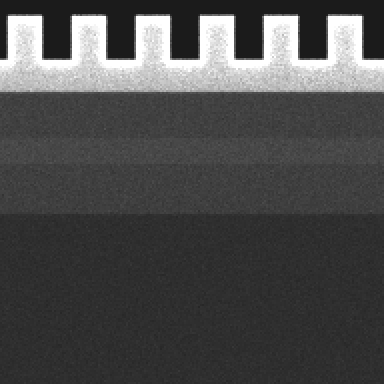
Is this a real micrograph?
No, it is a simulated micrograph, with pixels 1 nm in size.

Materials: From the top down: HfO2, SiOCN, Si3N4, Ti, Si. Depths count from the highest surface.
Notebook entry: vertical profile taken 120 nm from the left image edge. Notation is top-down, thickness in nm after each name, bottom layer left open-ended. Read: empty 44, HfO2 32, SiOCN 46, Si3N4 26, Ti 50, Si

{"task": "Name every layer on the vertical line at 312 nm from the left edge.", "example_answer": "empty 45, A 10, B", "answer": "empty 44, HfO2 32, SiOCN 46, Si3N4 26, Ti 50, Si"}